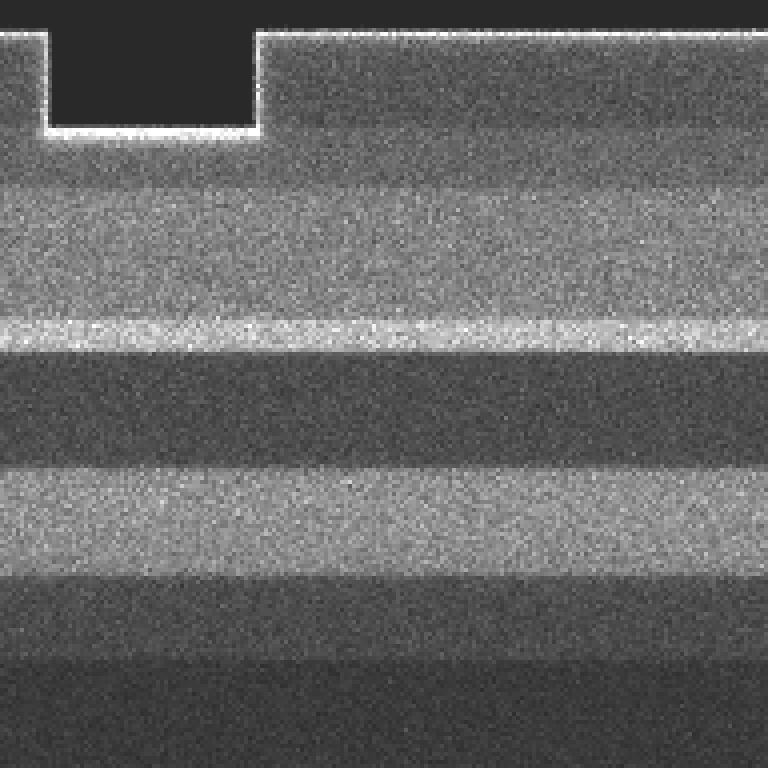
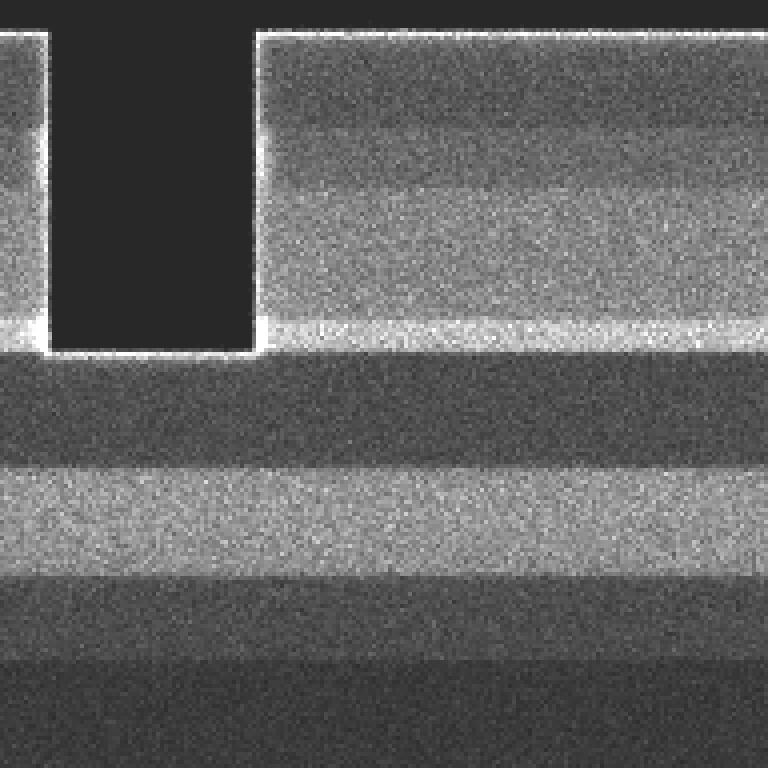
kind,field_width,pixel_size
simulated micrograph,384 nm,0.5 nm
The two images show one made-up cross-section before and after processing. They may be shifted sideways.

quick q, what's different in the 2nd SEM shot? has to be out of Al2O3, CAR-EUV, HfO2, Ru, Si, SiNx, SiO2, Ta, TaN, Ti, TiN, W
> HfO2 and Ru and SiO2 removed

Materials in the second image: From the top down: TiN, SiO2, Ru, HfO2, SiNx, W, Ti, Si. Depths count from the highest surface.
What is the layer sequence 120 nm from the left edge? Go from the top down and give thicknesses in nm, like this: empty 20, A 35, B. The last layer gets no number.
empty 160, SiNx 58, W 54, Ti 42, Si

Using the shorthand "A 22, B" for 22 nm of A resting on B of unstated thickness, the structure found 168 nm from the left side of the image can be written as TiN 48, SiO2 30, Ru 66, HfO2 16, SiNx 58, W 54, Ti 42, Si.